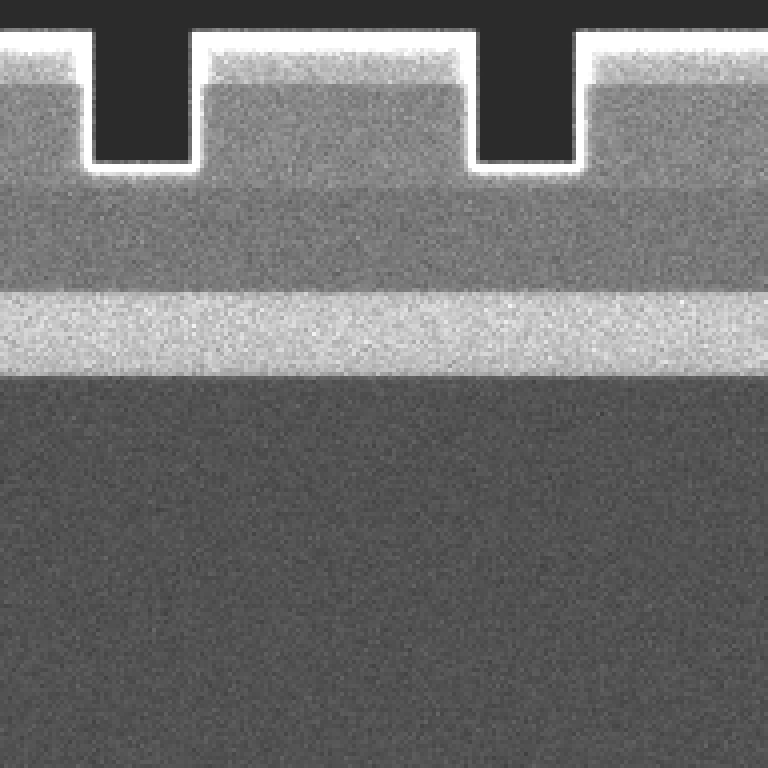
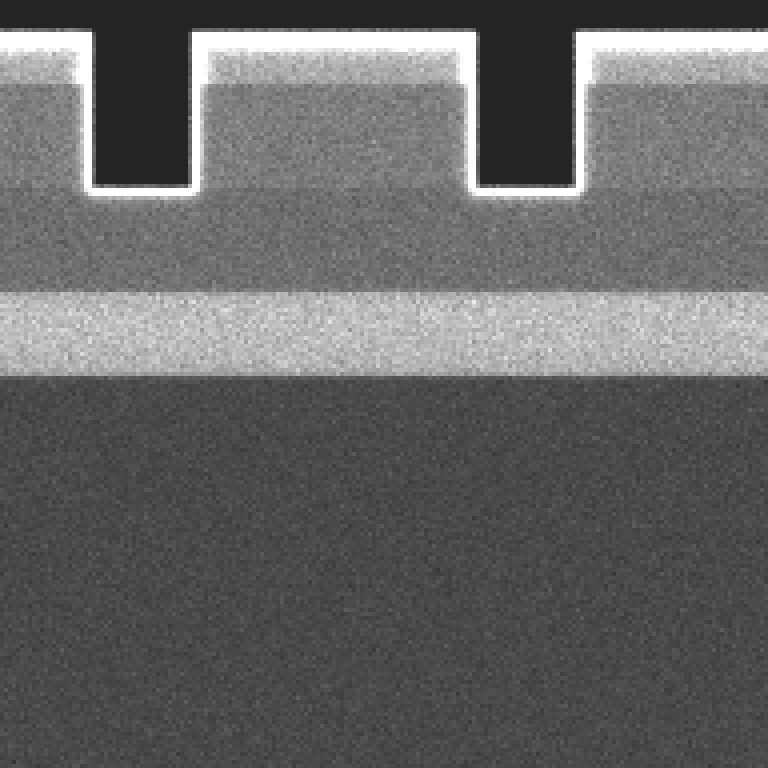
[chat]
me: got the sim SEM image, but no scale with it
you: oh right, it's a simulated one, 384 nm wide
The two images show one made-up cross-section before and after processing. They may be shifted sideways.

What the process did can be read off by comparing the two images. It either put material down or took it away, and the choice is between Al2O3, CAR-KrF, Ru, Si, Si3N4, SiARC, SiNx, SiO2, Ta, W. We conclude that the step removed Si3N4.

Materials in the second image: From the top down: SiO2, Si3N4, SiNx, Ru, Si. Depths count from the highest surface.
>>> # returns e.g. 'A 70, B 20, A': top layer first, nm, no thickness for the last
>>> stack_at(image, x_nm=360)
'SiO2 26, Si3N4 52, SiNx 52, Ru 42, Si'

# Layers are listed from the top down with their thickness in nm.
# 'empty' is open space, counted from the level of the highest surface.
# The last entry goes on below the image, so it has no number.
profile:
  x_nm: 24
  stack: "SiO2 26, Si3N4 52, SiNx 52, Ru 42, Si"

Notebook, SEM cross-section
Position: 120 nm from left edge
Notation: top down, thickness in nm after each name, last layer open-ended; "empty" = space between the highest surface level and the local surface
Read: SiO2 26, Si3N4 52, SiNx 52, Ru 42, Si